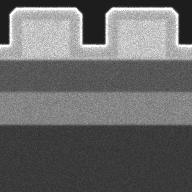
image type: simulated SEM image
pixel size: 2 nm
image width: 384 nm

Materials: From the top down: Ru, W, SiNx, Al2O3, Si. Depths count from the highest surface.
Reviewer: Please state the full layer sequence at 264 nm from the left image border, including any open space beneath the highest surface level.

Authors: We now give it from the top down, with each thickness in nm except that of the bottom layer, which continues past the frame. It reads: Ru 24, W 80, SiNx 64, Al2O3 66, Si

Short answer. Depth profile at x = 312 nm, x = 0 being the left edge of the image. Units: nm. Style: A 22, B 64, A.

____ Ru 24, W 80, SiNx 64, Al2O3 66, Si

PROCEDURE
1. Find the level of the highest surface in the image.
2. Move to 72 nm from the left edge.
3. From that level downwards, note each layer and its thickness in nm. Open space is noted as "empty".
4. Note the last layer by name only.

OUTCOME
Ru 24, W 80, SiNx 64, Al2O3 66, Si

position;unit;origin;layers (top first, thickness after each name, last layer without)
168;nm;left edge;empty 74, Ru 24, W 6, SiNx 64, Al2O3 66, Si